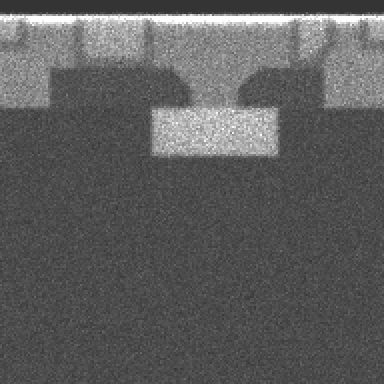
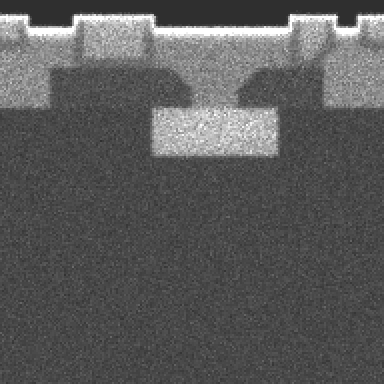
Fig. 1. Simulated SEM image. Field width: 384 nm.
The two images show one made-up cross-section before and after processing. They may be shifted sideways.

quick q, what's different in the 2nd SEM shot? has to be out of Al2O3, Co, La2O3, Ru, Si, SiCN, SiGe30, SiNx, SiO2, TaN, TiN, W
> SiO2 removed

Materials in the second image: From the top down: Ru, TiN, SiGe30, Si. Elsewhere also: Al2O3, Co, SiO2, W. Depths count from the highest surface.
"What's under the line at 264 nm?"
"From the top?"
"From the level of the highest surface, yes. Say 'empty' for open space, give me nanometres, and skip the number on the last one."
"empty 12, SiO2 40, SiGe30 40, W 48, Si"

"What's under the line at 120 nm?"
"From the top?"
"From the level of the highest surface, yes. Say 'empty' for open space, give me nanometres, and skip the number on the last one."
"Ru 42, TiN 10, SiGe30 40, Si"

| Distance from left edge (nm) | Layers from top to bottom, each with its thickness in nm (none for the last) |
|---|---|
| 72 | empty 12, SiO2 40, SiGe30 40, Si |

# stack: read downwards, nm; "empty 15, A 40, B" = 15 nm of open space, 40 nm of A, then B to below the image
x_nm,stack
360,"TiN 34, Co 58, Si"